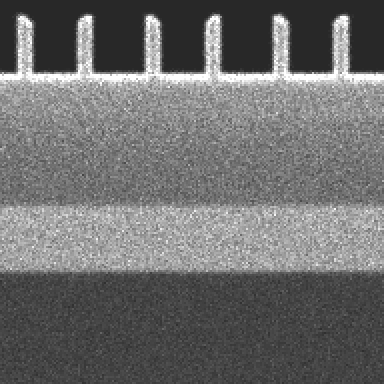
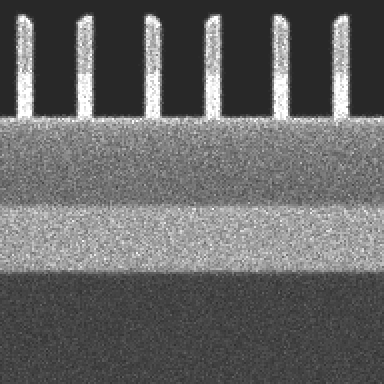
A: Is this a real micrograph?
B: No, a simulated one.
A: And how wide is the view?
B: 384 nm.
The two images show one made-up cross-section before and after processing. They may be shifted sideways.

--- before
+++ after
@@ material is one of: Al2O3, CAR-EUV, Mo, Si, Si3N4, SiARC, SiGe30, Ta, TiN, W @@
Al2O3 removed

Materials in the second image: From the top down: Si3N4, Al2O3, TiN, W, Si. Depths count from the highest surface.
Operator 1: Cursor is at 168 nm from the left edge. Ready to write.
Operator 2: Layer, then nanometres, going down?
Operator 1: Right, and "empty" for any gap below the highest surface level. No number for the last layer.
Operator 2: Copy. empty 102, TiN 88, W 66, Si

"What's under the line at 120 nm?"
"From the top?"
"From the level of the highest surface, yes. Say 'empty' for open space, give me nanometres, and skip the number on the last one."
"empty 102, TiN 88, W 66, Si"